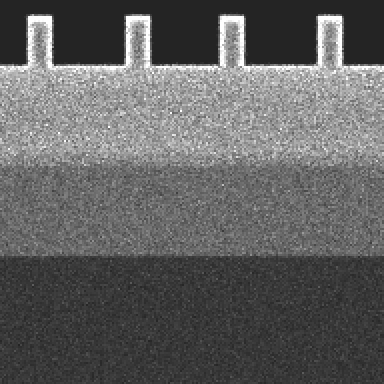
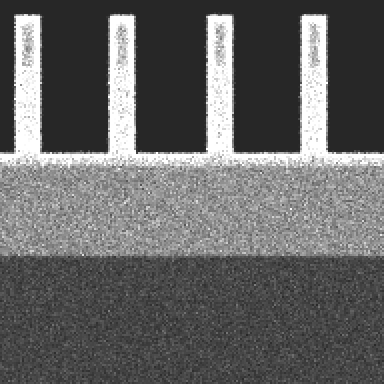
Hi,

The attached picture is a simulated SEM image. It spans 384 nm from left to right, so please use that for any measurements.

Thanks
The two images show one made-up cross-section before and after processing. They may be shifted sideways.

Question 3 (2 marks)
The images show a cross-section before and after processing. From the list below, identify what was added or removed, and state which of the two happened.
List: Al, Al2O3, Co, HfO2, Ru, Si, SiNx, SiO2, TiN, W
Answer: W was removed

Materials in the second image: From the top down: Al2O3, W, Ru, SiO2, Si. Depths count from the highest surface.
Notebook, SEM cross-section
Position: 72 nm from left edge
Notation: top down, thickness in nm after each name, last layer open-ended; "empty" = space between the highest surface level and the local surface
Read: empty 138, Ru 12, SiO2 90, Si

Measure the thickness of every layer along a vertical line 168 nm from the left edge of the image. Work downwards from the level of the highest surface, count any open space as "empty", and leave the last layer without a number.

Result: empty 138, Ru 12, SiO2 90, Si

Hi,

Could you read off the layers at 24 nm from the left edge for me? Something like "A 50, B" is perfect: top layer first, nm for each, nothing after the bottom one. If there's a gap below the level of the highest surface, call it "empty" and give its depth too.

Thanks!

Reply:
Al2O3 50, W 88, Ru 12, SiO2 90, Si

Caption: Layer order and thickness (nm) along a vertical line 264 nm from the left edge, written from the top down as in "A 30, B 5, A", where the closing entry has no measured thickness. empty 138, Ru 12, SiO2 90, Si